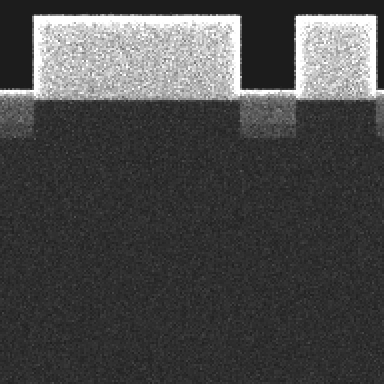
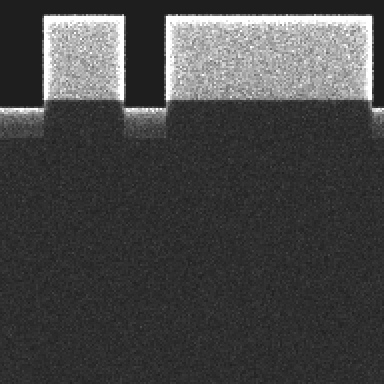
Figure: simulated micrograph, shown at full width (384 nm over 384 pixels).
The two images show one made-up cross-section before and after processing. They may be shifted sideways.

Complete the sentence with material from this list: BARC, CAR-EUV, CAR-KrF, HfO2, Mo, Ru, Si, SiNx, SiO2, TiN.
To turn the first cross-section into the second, SiO2 must be removed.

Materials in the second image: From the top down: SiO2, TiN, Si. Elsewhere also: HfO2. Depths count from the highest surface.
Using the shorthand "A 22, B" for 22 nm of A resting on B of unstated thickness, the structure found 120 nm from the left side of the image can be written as HfO2 84, Si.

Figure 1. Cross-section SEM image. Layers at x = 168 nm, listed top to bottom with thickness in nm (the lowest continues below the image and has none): HfO2 84, Si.